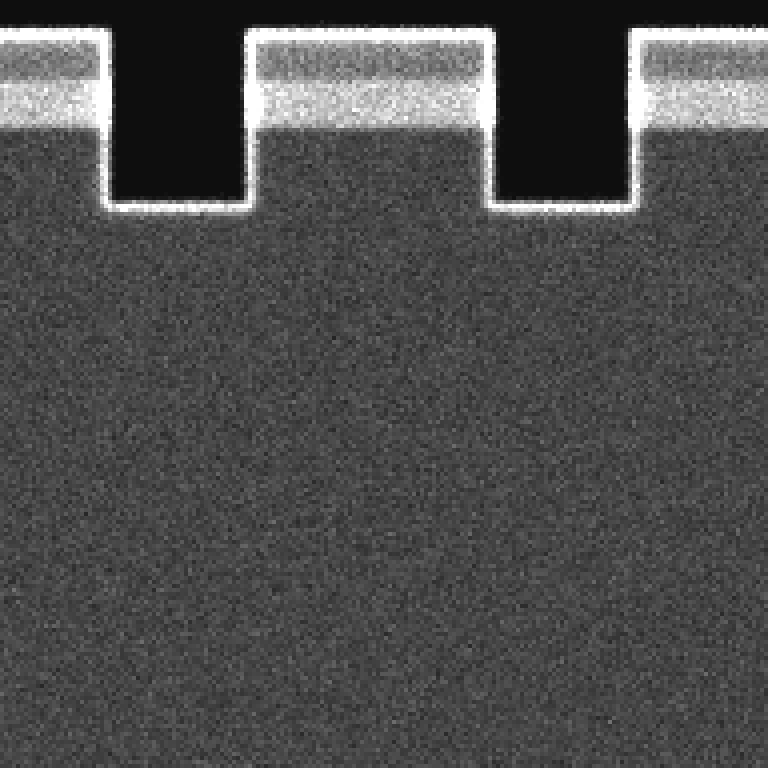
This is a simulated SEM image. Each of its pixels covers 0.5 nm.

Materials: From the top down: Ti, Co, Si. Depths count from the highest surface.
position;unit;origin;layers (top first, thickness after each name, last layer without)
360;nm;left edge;Ti 24, Co 24, Si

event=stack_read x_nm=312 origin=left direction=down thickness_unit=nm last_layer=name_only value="empty 86, Si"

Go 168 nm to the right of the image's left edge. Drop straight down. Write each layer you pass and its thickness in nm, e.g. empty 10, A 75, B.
Ti 24, Co 24, Si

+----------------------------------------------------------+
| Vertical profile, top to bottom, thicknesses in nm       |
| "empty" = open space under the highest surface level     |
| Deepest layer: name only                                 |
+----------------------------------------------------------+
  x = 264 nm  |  empty 86, Si